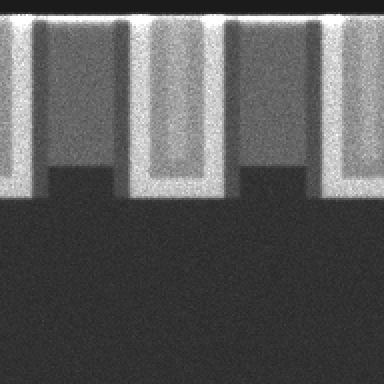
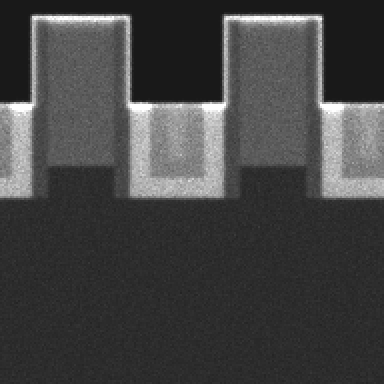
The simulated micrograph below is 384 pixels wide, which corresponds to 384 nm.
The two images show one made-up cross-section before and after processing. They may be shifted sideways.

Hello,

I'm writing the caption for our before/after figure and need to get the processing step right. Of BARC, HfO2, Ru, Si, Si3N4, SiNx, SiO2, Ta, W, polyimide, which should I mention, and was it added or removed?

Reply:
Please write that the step removed HfO2 and Ru and W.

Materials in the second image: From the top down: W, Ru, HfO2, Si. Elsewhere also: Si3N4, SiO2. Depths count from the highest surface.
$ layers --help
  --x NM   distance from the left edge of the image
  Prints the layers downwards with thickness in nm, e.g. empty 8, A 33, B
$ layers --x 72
SiO2 150, Si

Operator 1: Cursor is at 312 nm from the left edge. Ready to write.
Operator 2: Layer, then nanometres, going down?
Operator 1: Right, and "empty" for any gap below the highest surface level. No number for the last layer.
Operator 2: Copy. Si3N4 182, Si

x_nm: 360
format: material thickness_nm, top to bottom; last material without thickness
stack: empty 88, W 56, Ru 18, HfO2 20, Si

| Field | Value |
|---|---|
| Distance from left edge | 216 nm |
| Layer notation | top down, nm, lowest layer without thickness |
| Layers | empty 88, HfO2 94, Si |